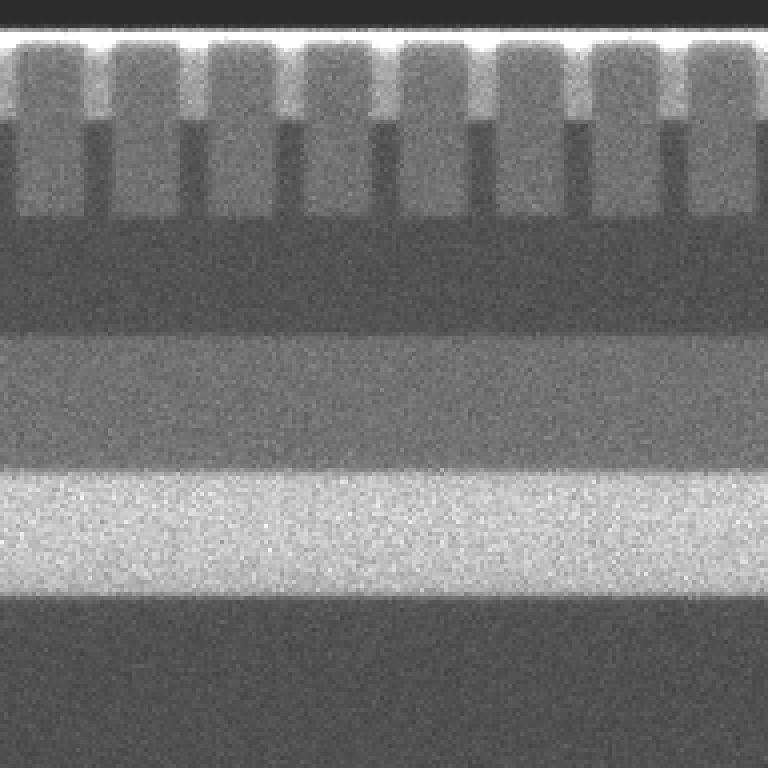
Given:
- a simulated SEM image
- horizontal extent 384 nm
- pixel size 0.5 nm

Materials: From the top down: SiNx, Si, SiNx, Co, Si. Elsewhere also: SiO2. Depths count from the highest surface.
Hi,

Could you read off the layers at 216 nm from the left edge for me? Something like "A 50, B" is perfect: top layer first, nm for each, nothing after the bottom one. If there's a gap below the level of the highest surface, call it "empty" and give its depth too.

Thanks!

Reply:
SiNx 92, Si 60, SiNx 68, Co 62, Si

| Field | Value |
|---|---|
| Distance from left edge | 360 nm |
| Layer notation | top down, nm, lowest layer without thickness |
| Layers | SiNx 92, Si 60, SiNx 68, Co 62, Si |